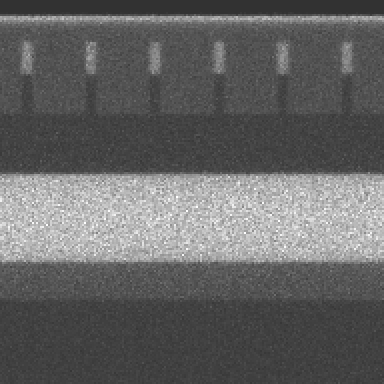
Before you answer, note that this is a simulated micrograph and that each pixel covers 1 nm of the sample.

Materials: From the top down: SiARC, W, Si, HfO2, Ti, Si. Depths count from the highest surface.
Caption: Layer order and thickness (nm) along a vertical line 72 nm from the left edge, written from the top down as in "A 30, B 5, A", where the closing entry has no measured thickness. SiARC 98, Si 60, HfO2 88, Ti 38, Si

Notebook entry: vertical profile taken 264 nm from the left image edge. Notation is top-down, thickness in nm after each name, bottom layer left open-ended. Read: SiARC 98, Si 60, HfO2 88, Ti 38, Si